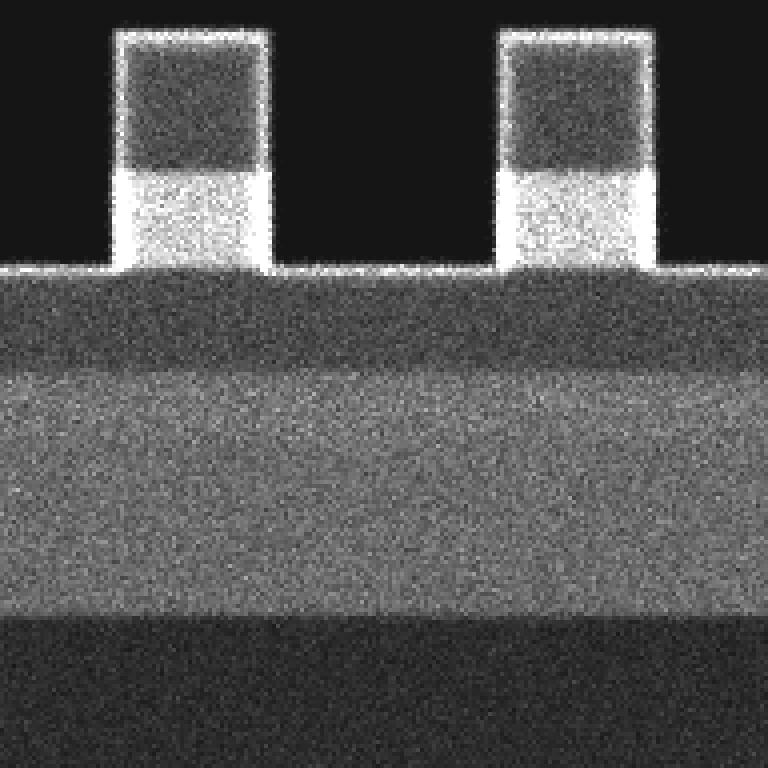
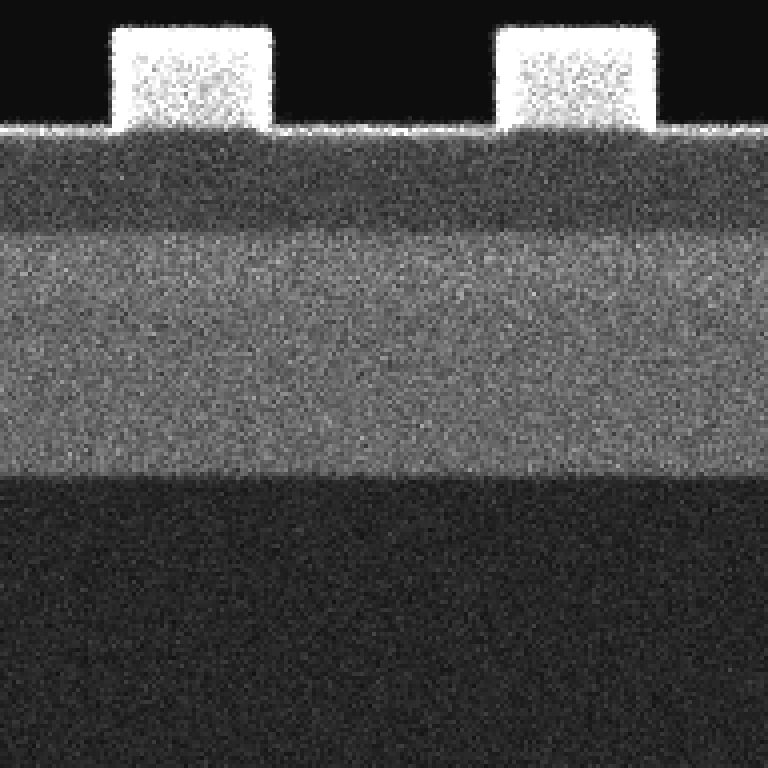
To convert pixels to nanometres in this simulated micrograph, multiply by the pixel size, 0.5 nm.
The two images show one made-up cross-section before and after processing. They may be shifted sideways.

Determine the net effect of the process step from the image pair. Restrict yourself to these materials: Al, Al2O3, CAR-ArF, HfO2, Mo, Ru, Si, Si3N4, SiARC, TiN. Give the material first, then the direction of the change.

SiARC: removed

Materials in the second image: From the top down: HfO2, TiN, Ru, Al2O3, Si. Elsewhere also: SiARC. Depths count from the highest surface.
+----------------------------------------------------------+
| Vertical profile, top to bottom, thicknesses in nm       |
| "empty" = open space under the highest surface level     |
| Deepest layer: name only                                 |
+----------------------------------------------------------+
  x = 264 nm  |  HfO2 48, TiN 52, Ru 34, Al2O3 88, Si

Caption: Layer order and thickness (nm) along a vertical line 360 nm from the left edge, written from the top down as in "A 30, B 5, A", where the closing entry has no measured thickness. empty 48, TiN 52, Ru 34, Al2O3 88, Si